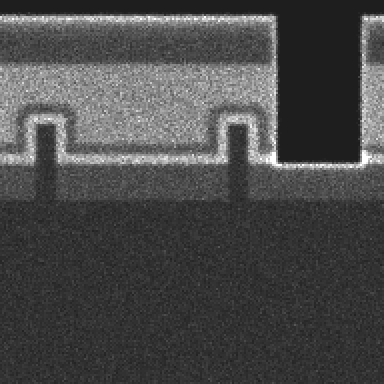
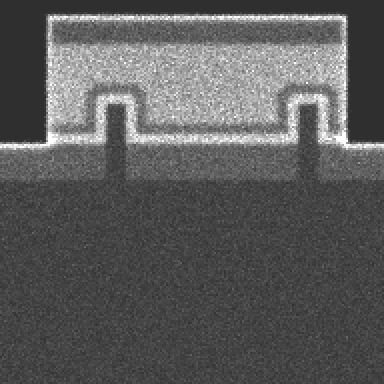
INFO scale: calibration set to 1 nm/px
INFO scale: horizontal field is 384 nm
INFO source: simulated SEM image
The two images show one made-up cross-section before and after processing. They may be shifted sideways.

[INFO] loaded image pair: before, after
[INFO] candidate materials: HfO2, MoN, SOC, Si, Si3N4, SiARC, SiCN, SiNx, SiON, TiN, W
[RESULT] removed SOC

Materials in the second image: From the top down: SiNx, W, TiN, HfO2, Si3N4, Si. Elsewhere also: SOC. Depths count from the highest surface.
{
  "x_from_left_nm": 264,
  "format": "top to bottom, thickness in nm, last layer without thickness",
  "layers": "SiNx 28, W 80, TiN 10, HfO2 10, Si3N4 36, Si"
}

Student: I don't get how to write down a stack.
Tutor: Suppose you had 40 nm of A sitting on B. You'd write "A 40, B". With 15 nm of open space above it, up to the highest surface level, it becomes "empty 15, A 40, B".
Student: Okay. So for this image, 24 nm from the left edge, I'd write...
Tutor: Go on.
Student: empty 128, Si3N4 36, Si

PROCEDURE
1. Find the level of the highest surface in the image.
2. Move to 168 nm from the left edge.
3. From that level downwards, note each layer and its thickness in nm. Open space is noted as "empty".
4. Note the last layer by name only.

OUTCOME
SiNx 28, W 80, TiN 10, HfO2 10, Si3N4 36, Si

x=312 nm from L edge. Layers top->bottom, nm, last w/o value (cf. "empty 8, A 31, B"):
SiNx 28, W 40, TiN 10, HfO2 10, Si